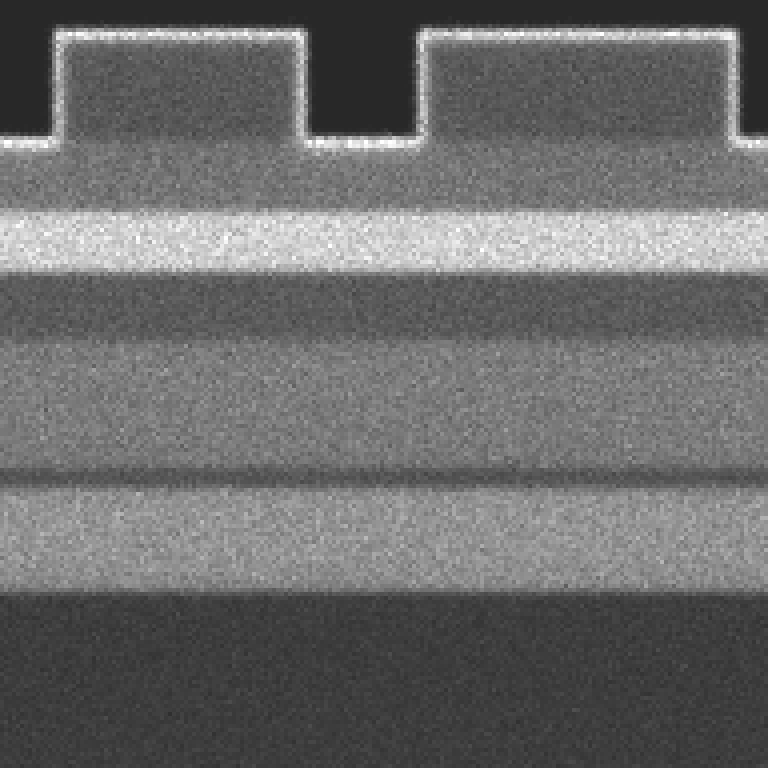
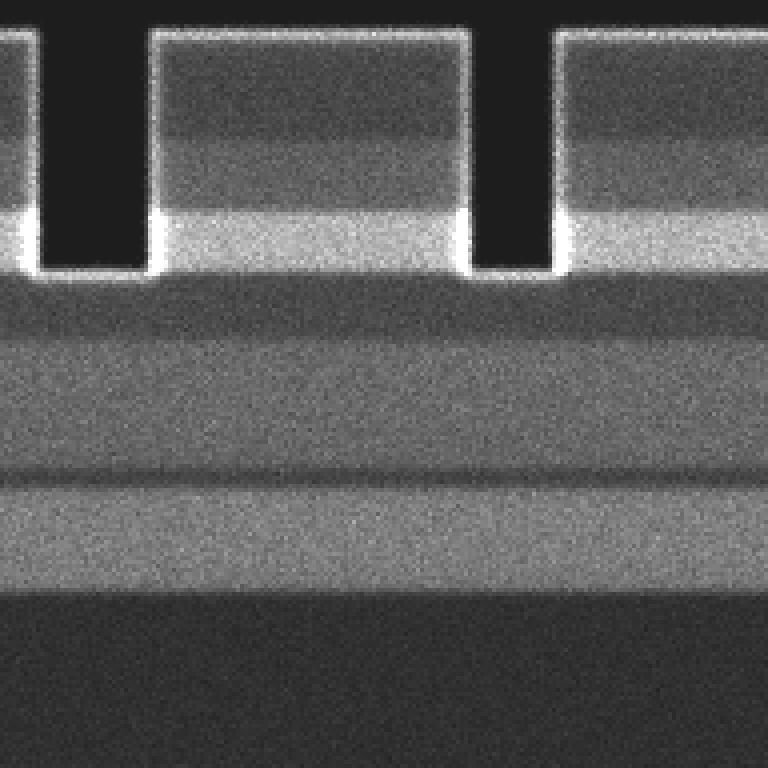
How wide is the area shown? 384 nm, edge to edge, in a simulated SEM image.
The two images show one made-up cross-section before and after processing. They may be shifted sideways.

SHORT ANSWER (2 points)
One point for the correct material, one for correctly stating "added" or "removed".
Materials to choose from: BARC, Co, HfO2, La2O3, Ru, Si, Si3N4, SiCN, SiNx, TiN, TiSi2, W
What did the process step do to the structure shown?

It removed Co and HfO2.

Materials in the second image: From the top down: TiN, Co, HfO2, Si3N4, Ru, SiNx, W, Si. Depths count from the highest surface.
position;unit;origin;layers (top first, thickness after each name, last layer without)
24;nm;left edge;empty 120, Si3N4 34, Ru 64, SiNx 10, W 52, Si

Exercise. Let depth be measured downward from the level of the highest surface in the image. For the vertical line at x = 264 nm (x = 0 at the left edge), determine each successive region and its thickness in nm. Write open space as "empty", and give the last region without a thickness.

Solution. empty 120, Si3N4 34, Ru 64, SiNx 10, W 52, Si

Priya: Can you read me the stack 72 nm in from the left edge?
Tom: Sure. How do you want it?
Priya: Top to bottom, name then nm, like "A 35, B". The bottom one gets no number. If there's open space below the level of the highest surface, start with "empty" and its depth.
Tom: empty 120, Si3N4 34, Ru 64, SiNx 10, W 52, Si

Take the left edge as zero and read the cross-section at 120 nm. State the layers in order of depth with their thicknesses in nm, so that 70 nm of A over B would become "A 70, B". TiN 54, Co 36, HfO2 30, Si3N4 34, Ru 64, SiNx 10, W 52, Si